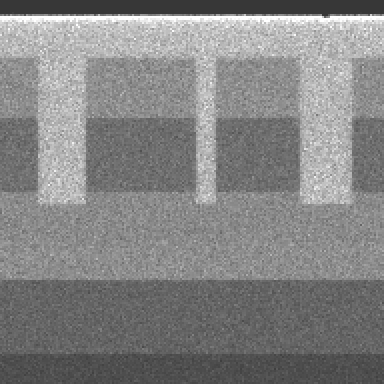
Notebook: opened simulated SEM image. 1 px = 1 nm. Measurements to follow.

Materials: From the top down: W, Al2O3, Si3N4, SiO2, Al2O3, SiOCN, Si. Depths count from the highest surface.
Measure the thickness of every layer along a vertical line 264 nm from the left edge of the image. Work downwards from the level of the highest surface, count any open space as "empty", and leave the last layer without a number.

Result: W 42, Al2O3 60, Si3N4 74, SiO2 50, Al2O3 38, SiOCN 74, Si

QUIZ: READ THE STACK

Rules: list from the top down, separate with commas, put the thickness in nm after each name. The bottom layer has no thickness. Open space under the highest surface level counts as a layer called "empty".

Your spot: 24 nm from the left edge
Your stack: W 42, Al2O3 60, Si3N4 74, SiO2 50, Al2O3 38, SiOCN 74, Si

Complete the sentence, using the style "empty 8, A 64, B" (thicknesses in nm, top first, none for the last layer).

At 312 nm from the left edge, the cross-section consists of W 188, SiO2 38, Al2O3 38, SiOCN 74, Si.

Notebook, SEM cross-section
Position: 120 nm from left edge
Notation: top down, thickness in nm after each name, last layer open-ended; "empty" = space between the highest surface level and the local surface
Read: W 42, Al2O3 60, Si3N4 74, SiO2 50, Al2O3 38, SiOCN 74, Si